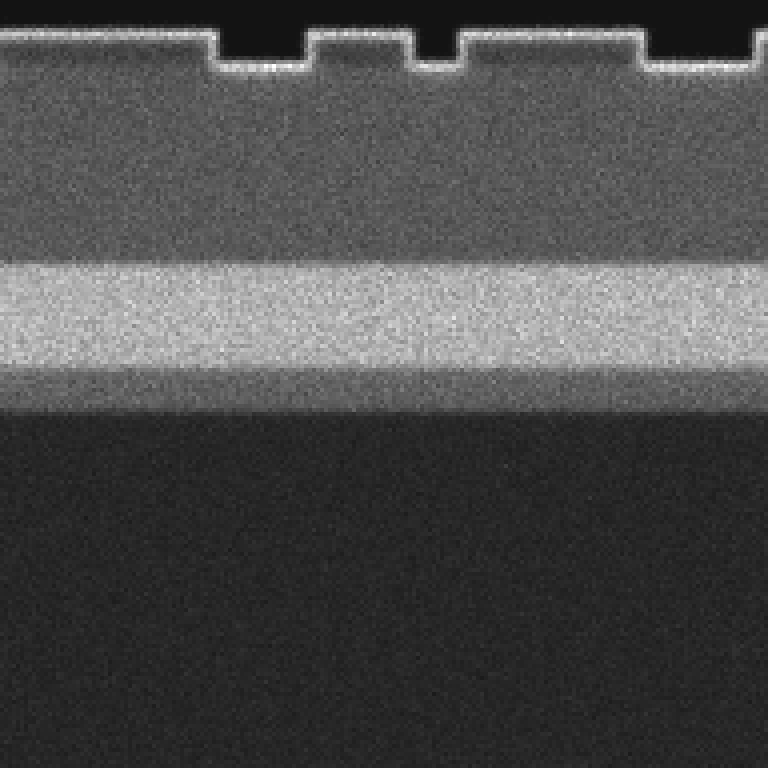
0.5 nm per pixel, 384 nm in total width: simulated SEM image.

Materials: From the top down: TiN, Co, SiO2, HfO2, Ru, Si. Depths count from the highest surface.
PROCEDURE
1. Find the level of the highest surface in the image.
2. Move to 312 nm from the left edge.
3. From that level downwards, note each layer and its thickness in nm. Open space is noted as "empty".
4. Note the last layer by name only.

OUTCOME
TiN 16, Co 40, SiO2 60, HfO2 52, Ru 22, Si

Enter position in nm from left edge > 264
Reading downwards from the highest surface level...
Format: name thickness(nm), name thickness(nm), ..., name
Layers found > TiN 16, Co 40, SiO2 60, HfO2 52, Ru 22, Si